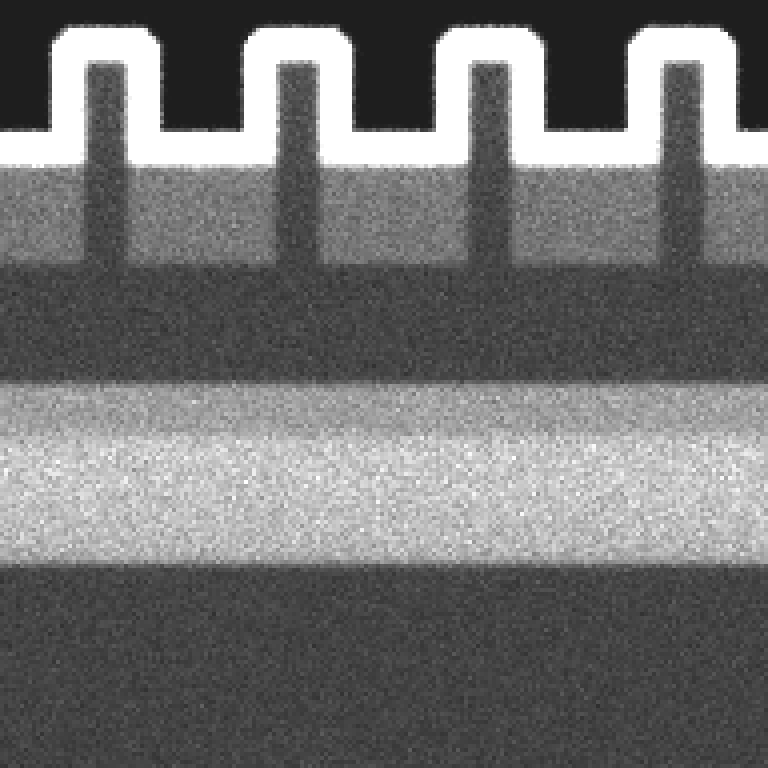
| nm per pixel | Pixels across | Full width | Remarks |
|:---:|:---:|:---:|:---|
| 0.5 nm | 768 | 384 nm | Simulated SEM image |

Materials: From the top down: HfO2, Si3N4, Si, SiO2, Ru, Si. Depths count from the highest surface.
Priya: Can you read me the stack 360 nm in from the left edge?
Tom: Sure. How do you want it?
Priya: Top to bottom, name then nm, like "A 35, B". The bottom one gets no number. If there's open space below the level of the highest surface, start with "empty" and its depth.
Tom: empty 2, HfO2 64, Si3N4 50, Si 60, SiO2 26, Ru 64, Si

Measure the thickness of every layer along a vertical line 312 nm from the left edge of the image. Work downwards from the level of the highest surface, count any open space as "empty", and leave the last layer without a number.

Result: empty 52, HfO2 14, Si3N4 50, Si 60, SiO2 26, Ru 64, Si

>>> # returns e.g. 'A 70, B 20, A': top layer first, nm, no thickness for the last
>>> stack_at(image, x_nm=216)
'empty 52, HfO2 14, Si3N4 50, Si 60, SiO2 26, Ru 64, Si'